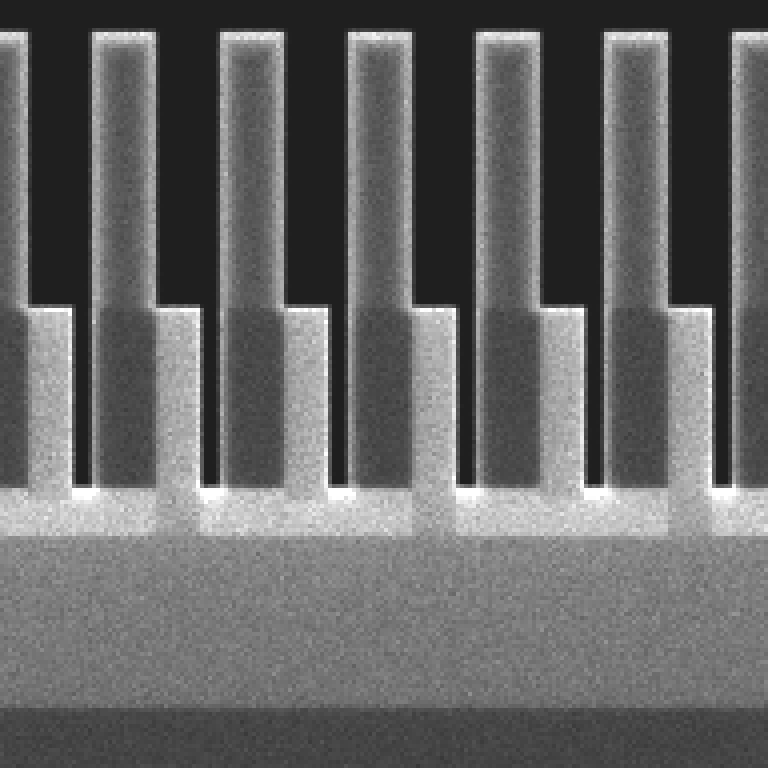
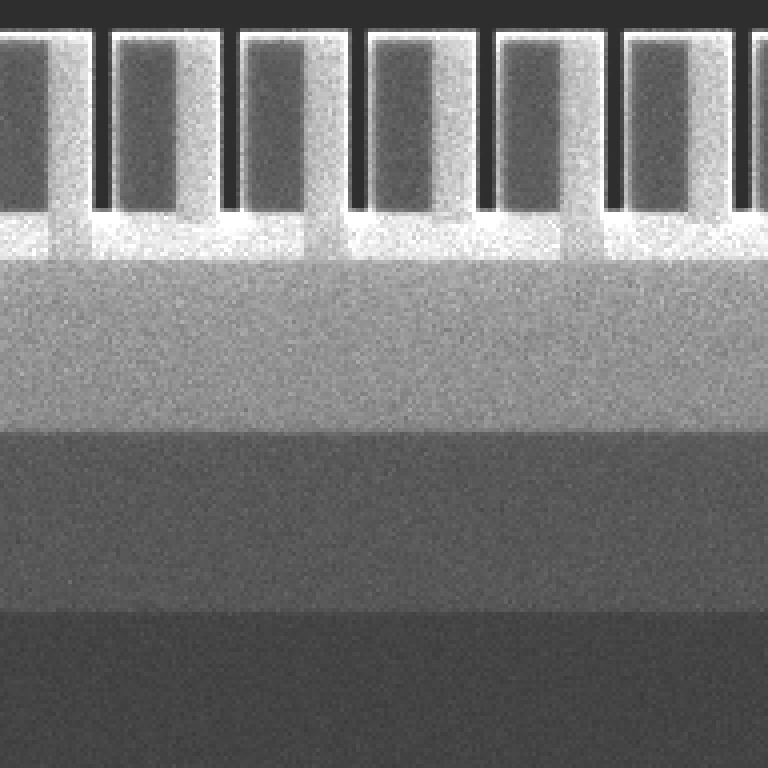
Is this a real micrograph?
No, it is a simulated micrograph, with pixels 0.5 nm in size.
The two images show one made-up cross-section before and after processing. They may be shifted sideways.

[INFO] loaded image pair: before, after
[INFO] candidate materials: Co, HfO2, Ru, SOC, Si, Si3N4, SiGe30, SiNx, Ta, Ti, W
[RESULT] removed SOC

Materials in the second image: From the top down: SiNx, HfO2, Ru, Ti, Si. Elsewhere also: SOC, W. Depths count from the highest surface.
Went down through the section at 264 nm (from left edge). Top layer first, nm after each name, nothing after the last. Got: SiNx 90, HfO2 24, Ru 86, Ti 90, Si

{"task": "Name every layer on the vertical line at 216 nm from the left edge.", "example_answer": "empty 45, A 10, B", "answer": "W 96, HfO2 18, Ru 86, Ti 90, Si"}